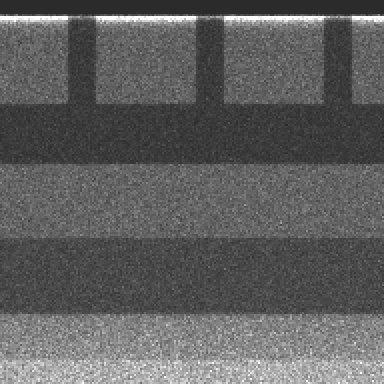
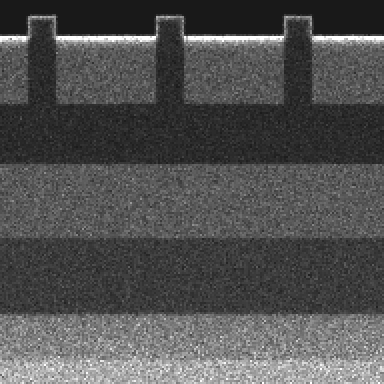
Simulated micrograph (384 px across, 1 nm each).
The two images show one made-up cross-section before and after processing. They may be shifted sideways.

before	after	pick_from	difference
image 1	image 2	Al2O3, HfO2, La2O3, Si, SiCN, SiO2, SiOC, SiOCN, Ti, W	SiO2 removed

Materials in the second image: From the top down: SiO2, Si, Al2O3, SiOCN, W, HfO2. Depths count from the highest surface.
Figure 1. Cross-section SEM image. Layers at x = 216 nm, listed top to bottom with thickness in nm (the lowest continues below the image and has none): empty 20, SiO2 68, Si 60, Al2O3 74, SiOCN 76, W 46, HfO2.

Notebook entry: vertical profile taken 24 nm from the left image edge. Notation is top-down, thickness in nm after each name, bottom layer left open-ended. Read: empty 20, SiO2 68, Si 60, Al2O3 74, SiOCN 76, W 46, HfO2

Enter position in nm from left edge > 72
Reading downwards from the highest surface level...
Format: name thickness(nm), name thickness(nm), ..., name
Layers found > empty 20, SiO2 68, Si 60, Al2O3 74, SiOCN 76, W 46, HfO2